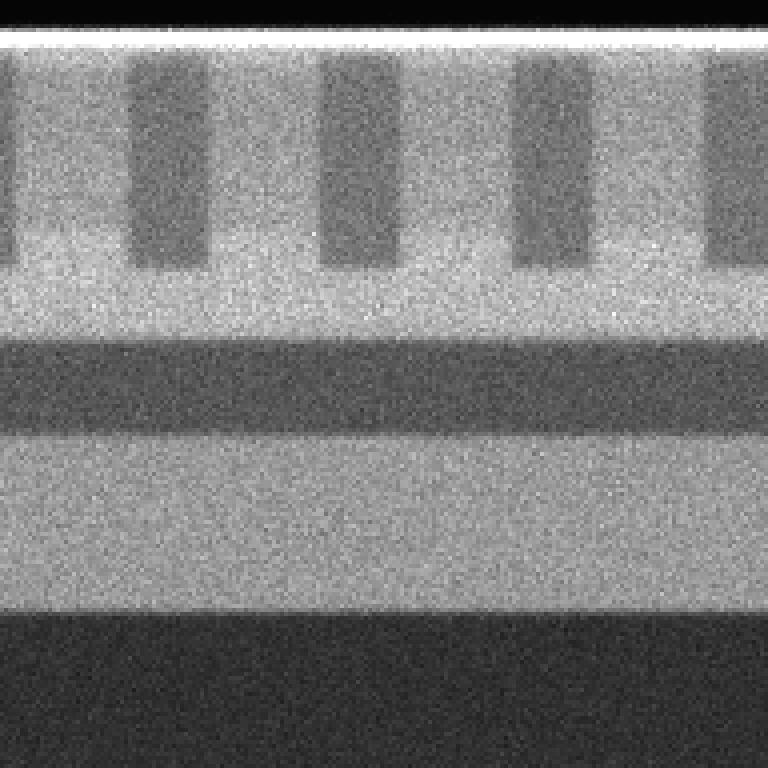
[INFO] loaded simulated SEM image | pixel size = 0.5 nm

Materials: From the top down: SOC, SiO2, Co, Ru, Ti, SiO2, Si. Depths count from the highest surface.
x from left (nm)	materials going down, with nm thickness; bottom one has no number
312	SOC 12, SiO2 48, Co 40, Ru 54, Ti 48, SiO2 88, Si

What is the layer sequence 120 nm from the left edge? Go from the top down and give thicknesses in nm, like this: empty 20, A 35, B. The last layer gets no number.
SOC 12, SiO2 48, Co 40, Ru 54, Ti 48, SiO2 88, Si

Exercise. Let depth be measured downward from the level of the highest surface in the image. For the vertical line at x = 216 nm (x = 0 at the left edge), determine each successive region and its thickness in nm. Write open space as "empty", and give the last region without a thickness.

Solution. SOC 12, SiO2 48, Co 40, Ru 54, Ti 48, SiO2 88, Si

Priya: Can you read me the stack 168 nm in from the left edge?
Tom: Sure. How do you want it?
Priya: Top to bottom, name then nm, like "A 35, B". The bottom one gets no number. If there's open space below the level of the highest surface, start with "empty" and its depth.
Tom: SOC 118, Ru 36, Ti 48, SiO2 88, Si